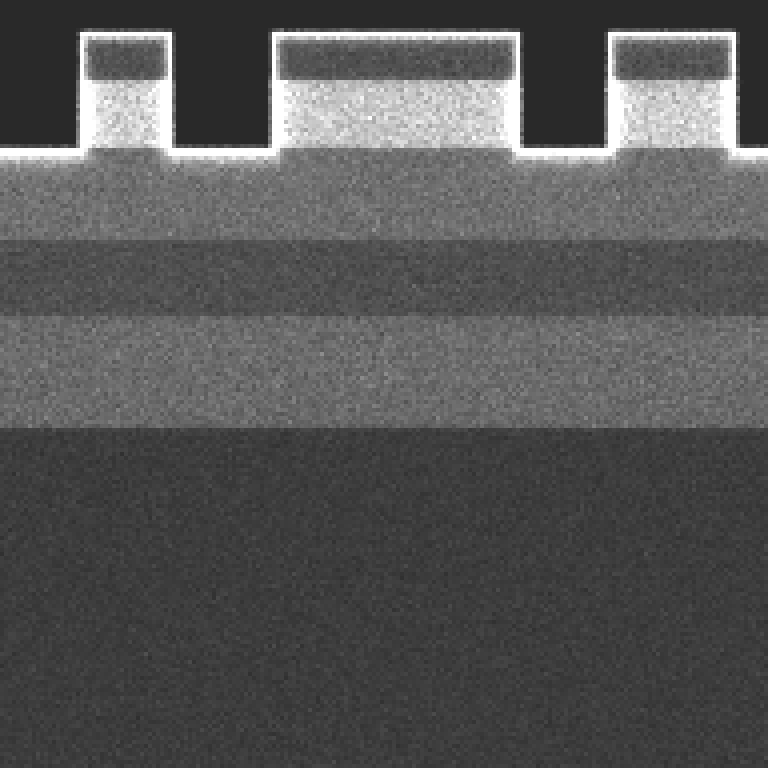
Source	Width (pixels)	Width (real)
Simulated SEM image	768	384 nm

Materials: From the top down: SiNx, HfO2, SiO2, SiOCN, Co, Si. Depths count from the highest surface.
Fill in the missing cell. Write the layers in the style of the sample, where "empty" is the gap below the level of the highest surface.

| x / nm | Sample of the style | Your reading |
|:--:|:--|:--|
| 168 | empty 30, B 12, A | SiNx 24, HfO2 34, SiO2 46, SiOCN 38, Co 56, Si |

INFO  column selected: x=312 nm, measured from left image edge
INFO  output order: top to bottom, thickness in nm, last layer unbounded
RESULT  SiNx 24, HfO2 34, SiO2 46, SiOCN 38, Co 56, Si